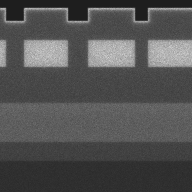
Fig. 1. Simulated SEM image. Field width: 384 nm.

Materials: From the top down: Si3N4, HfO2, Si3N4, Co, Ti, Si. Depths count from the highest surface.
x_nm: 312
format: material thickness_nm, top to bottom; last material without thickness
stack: Si3N4 64, HfO2 54, Si3N4 72, Co 78, Ti 38, Si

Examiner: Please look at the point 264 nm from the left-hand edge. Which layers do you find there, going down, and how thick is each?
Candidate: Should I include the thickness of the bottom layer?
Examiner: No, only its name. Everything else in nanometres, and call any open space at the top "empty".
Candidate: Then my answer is Si3N4 64, HfO2 54, Si3N4 72, Co 78, Ti 38, Si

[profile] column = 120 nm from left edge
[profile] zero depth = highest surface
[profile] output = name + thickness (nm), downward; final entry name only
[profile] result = Si3N4 64, HfO2 54, Si3N4 72, Co 78, Ti 38, Si